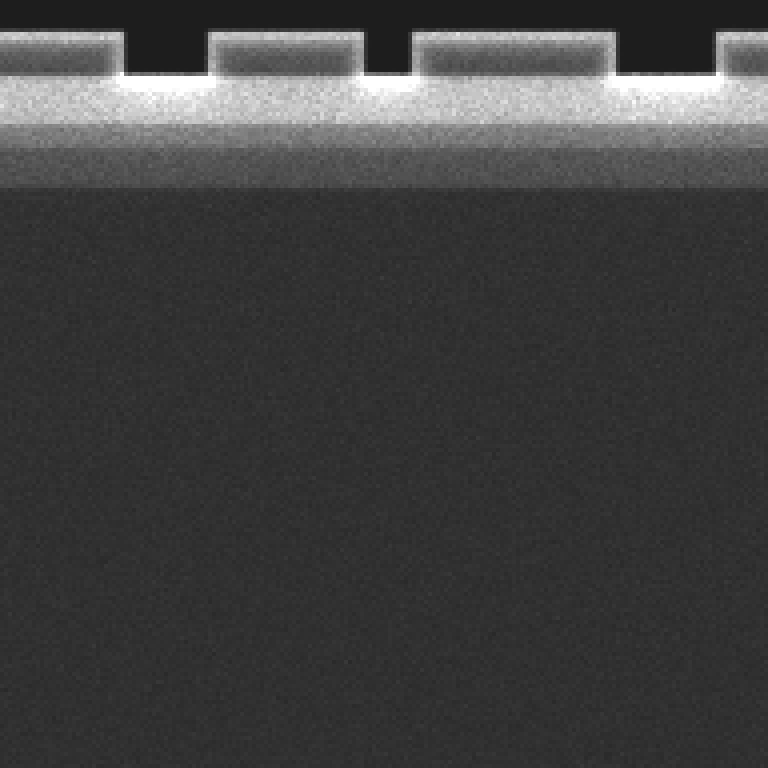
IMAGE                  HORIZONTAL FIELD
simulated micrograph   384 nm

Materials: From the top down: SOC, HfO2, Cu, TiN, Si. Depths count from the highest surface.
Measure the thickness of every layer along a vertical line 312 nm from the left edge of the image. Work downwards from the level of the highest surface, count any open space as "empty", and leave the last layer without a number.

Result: empty 22, HfO2 24, Cu 12, TiN 20, Si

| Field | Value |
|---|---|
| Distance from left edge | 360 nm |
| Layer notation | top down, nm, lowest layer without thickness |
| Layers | SOC 22, HfO2 24, Cu 12, TiN 20, Si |